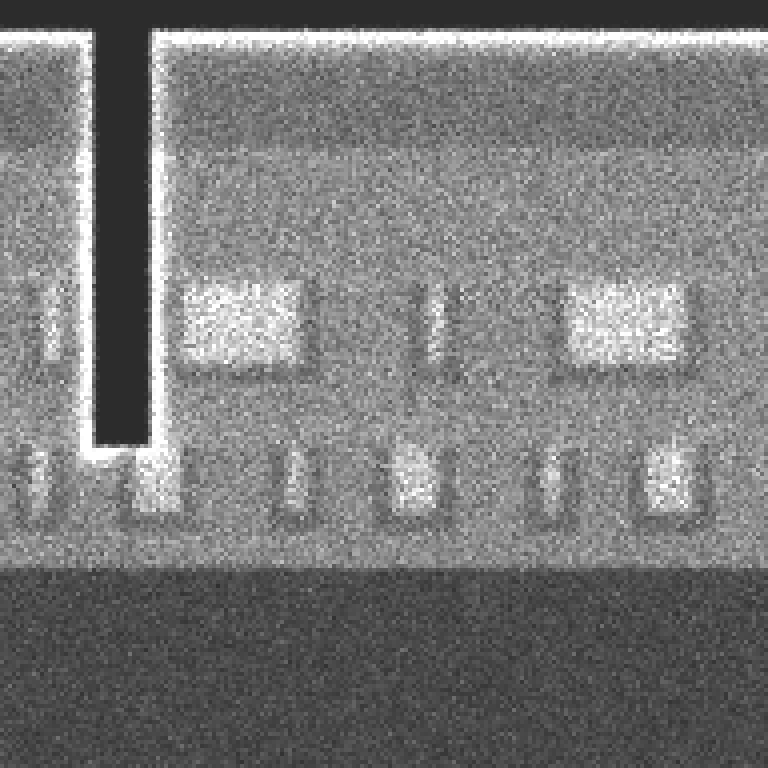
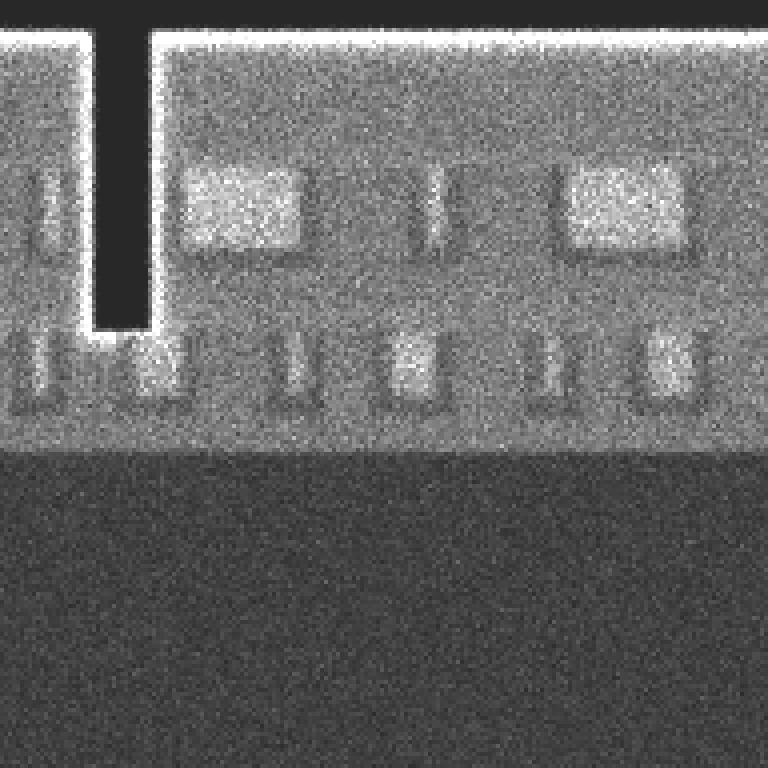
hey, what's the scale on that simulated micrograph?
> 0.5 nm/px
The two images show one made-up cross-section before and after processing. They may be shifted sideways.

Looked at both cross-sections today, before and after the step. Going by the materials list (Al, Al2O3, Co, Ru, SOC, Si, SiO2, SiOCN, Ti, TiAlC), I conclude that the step removed SOC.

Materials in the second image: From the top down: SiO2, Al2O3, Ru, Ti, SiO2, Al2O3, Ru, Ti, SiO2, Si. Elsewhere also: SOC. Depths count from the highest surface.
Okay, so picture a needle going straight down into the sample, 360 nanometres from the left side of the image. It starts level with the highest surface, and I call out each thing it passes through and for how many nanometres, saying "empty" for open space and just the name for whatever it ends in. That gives SiO2 60, Al2O3 8, SiO2 68, Al2O3 14, SiO2 60, Si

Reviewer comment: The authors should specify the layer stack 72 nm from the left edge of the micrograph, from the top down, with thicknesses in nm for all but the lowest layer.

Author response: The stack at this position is empty 150, Ru 32, Ti 10, SiO2 18, Si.